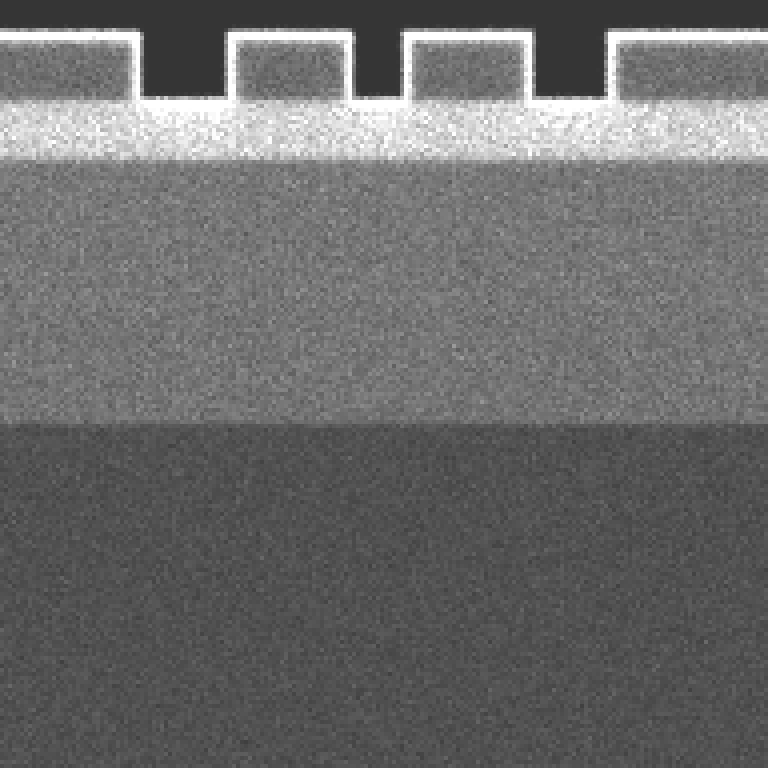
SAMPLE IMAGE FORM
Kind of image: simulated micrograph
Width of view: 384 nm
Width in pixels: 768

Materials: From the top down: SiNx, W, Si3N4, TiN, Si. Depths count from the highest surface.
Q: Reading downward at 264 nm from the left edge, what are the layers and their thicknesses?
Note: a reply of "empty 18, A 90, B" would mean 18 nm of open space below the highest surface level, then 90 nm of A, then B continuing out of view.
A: SiNx 34, W 30, Si3N4 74, TiN 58, Si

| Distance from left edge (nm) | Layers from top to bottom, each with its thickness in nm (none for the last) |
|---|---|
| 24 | SiNx 34, W 30, Si3N4 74, TiN 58, Si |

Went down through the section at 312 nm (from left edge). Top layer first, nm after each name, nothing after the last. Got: SiNx 34, W 30, Si3N4 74, TiN 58, Si